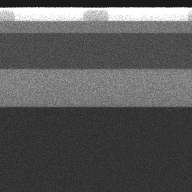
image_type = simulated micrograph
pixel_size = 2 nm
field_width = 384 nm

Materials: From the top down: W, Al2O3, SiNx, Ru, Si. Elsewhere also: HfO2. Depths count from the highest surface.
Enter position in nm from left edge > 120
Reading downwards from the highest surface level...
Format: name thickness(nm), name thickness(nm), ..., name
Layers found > HfO2 26, Al2O3 24, SiNx 72, Ru 76, Si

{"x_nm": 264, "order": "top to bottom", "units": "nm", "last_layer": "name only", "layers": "HfO2 26, Al2O3 24, SiNx 72, Ru 76, Si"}